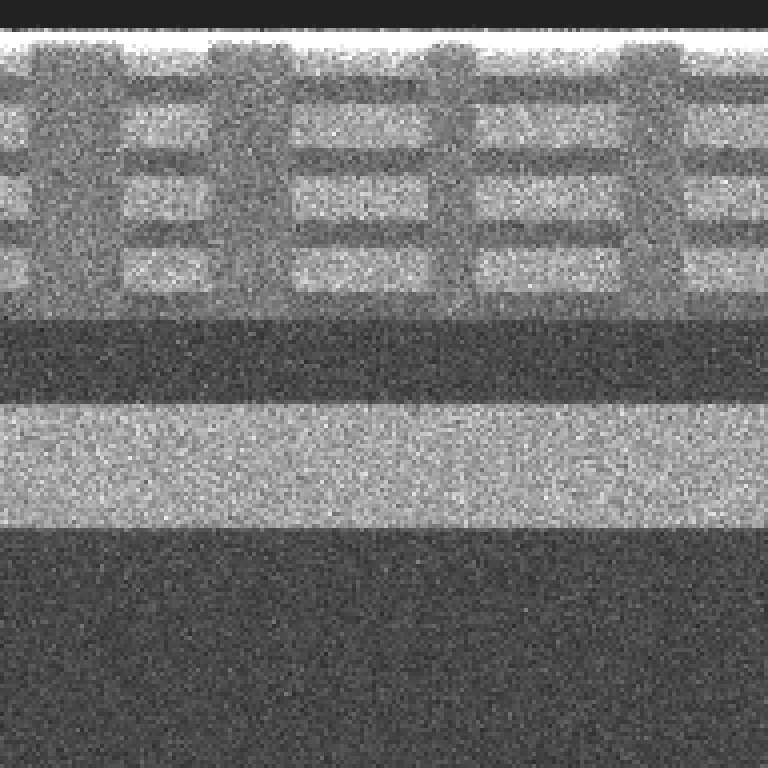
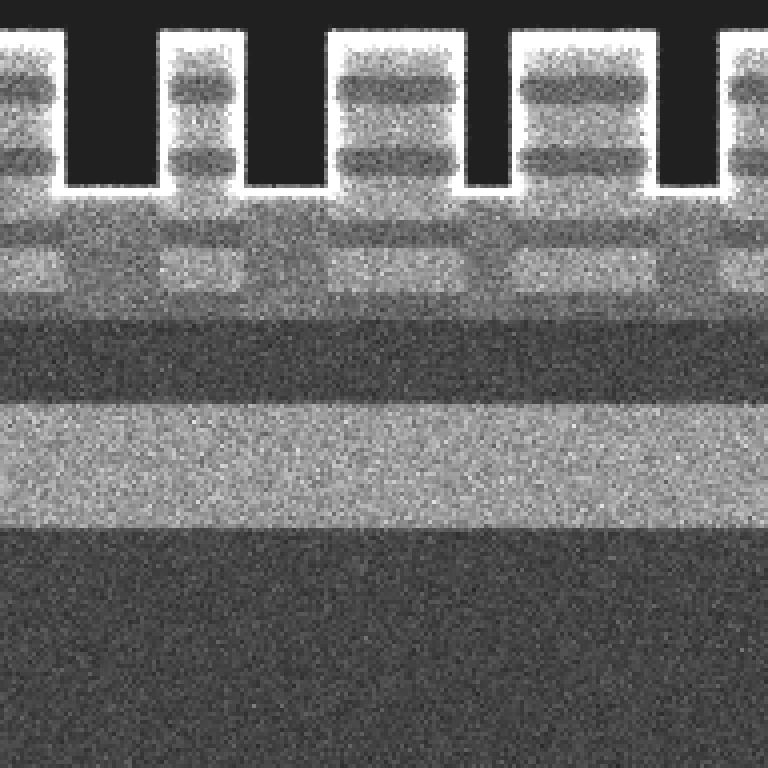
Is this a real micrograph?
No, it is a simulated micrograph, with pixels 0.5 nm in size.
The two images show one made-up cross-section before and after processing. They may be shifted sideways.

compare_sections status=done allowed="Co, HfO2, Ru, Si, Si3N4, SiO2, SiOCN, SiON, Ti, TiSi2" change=removed material="Si3N4"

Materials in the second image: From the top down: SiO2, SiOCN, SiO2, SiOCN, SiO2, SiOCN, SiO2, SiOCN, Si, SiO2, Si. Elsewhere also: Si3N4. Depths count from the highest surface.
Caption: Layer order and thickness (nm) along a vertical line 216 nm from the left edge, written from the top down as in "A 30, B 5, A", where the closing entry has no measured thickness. SiO2 22, SiOCN 14, SiO2 22, SiOCN 14, SiO2 22, SiOCN 14, SiO2 22, SiOCN 14, Si 42, SiO2 62, Si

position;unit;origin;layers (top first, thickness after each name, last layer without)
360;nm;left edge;SiO2 22, SiOCN 14, SiO2 22, SiOCN 14, SiO2 22, SiOCN 14, SiO2 22, SiOCN 14, Si 42, SiO2 62, Si